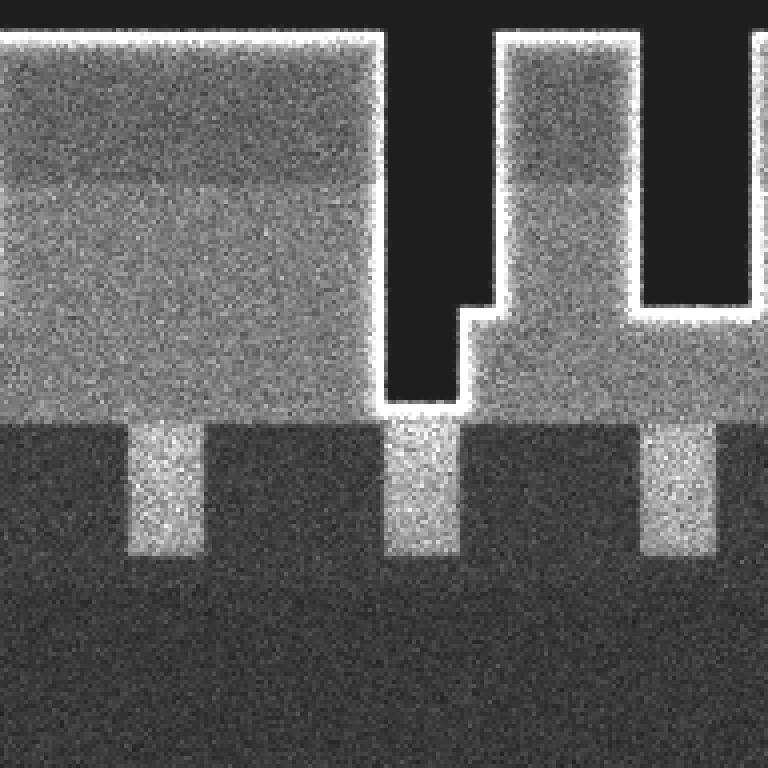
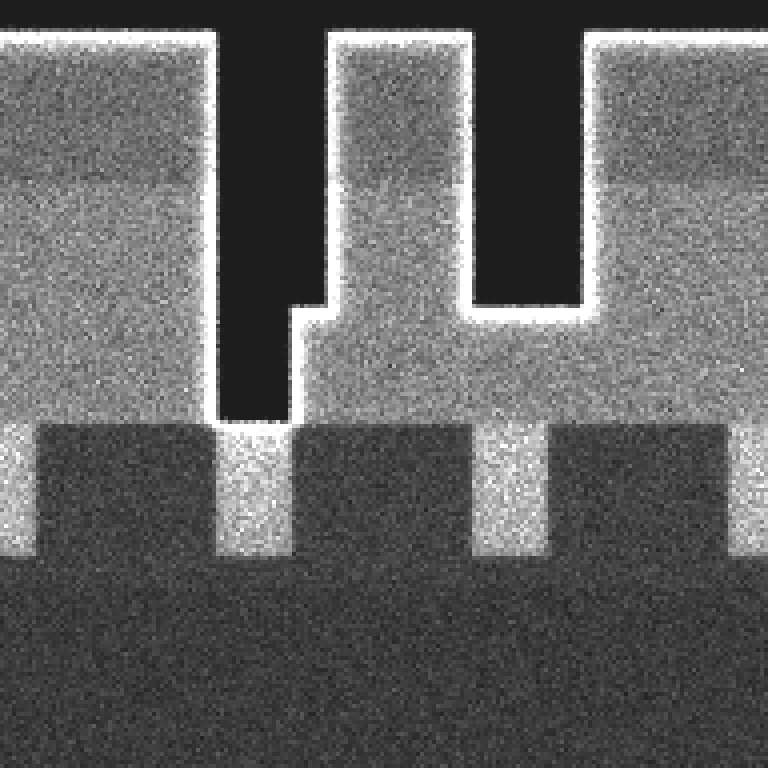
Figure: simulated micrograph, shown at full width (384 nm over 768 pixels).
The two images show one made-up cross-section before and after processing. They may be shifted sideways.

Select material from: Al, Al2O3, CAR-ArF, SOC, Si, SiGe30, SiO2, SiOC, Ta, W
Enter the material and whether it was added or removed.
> Al2O3 / removed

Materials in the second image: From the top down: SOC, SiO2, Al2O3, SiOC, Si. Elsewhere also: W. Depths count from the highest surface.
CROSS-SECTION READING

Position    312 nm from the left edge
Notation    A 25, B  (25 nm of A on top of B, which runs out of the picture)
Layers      SOC 76, SiO2 110, Al2O3 10, SiOC 82, Si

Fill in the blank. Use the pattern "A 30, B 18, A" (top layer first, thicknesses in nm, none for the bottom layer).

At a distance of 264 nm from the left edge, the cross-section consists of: empty 138, SiO2 48, Al2O3 10, W 66, SiOC 16, Si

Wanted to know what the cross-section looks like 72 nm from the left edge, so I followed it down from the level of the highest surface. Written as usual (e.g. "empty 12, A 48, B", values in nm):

SOC 76, SiO2 110, Al2O3 10, SiOC 82, Si